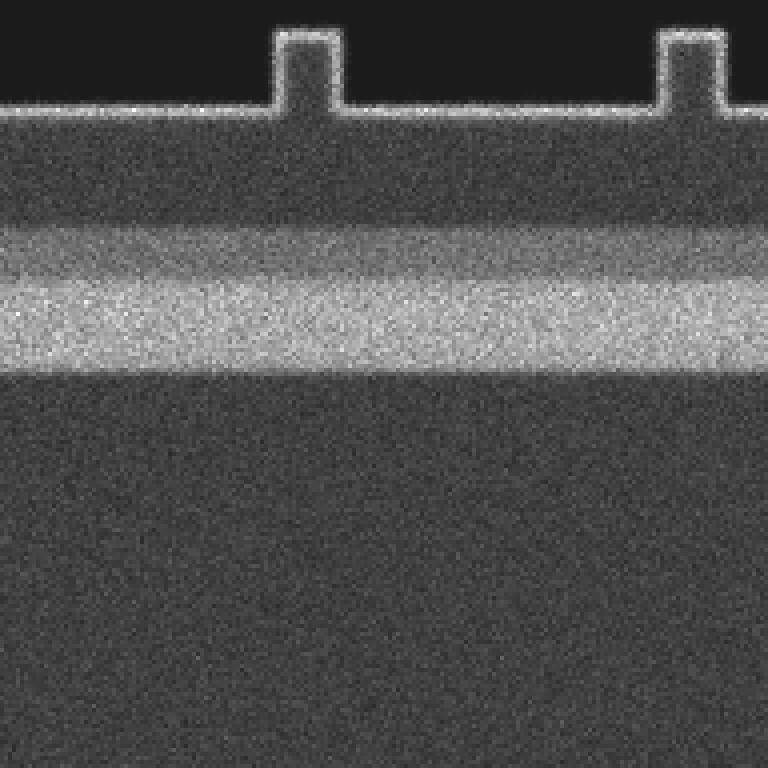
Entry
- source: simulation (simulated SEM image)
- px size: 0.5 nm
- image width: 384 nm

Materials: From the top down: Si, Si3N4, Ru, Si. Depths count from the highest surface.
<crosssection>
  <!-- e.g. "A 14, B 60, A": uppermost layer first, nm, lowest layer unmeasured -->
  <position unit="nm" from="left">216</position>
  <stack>empty 38, Si 60, Si3N4 26, Ru 46, Si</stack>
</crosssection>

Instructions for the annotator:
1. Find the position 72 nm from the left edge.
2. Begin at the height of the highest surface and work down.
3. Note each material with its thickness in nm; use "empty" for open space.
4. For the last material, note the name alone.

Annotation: empty 38, Si 60, Si3N4 26, Ru 46, Si